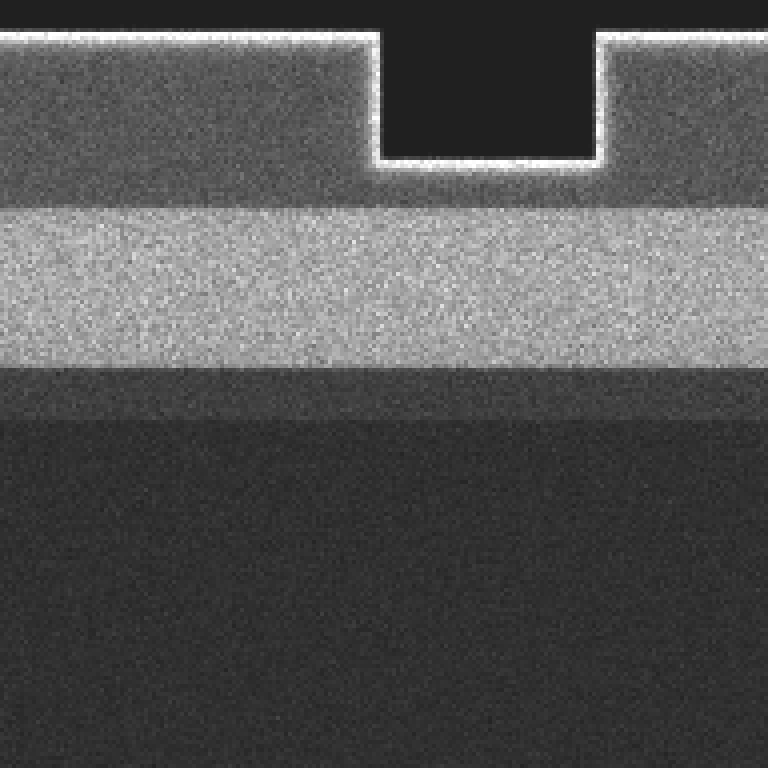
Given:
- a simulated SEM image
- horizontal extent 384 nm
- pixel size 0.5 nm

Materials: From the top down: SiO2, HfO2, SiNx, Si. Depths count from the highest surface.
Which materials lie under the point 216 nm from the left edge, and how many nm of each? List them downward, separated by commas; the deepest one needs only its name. empty 64, SiO2 24, HfO2 80, SiNx 26, Si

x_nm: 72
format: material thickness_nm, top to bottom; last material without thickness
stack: SiO2 88, HfO2 80, SiNx 26, Si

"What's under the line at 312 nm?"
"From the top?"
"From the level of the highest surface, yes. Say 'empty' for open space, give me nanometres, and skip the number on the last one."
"SiO2 88, HfO2 80, SiNx 26, Si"